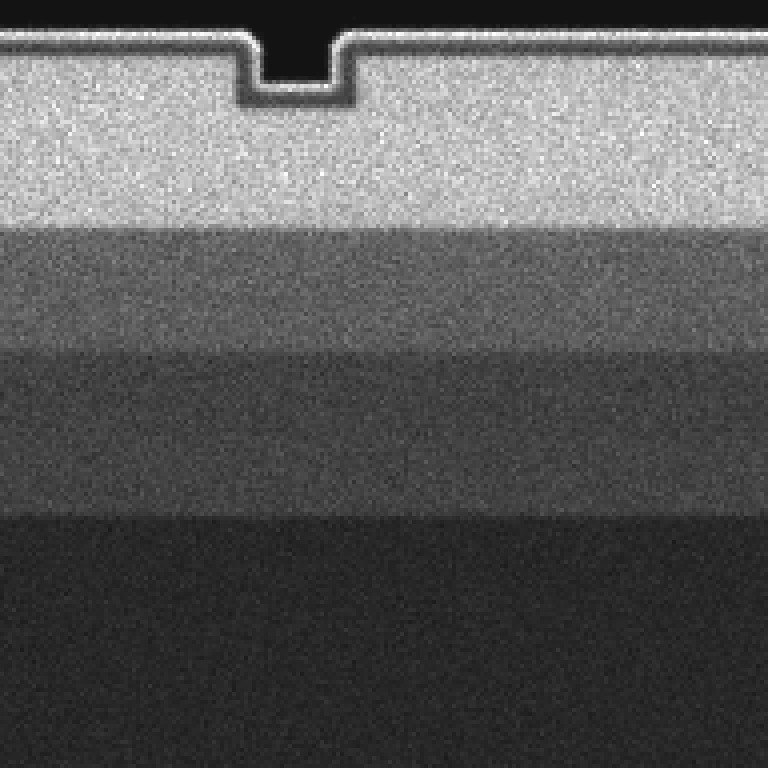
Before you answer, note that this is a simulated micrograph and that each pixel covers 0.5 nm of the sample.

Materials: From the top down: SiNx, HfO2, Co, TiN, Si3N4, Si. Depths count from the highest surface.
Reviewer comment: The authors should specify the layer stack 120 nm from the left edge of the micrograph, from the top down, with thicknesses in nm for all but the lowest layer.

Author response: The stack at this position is SiNx 38, HfO2 60, Co 62, TiN 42, Si3N4 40, Si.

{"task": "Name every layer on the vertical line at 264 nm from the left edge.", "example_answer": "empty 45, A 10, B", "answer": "SiNx 12, HfO2 86, Co 62, TiN 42, Si3N4 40, Si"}